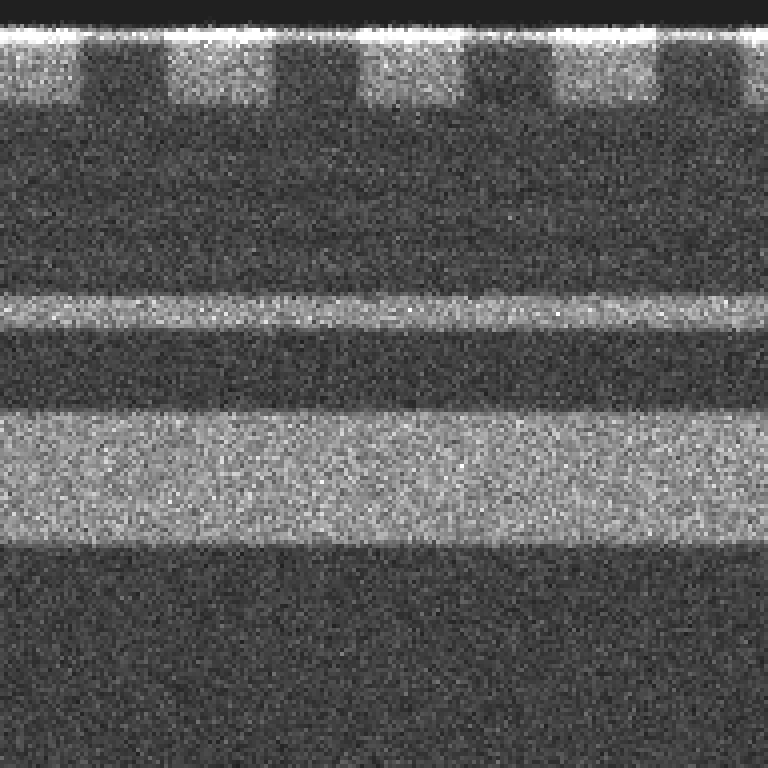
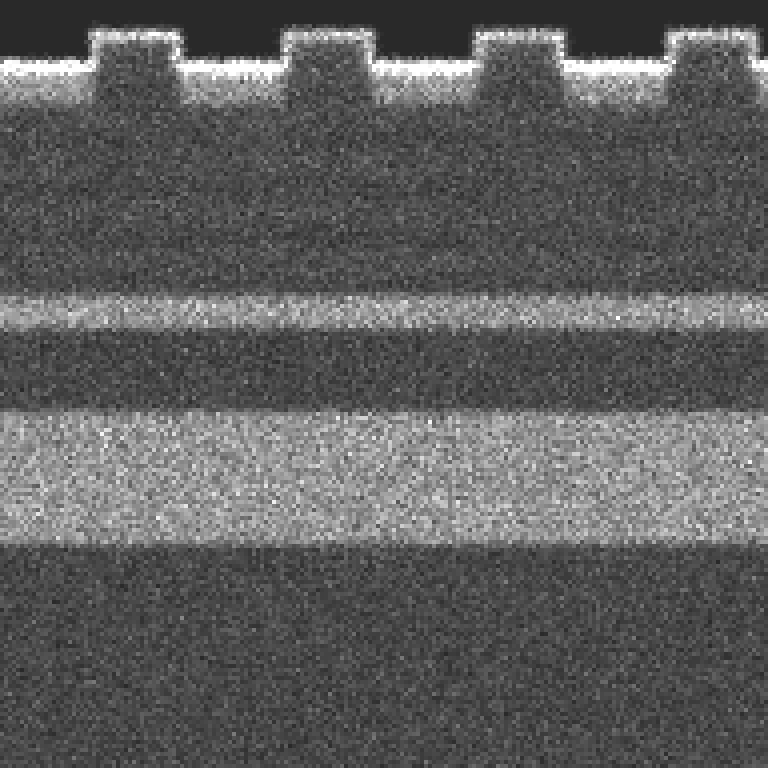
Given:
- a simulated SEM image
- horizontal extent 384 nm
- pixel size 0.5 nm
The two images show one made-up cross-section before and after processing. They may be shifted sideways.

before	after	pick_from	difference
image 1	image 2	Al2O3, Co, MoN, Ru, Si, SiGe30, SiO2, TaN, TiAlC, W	Co removed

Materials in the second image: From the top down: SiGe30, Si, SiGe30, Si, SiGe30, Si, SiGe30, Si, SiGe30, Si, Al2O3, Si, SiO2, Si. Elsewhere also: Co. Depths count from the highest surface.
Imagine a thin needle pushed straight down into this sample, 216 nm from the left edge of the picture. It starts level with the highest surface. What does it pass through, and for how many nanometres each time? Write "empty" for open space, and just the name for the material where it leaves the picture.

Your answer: empty 16, Co 20, SiGe30 14, Si 10, SiGe30 14, Si 10, SiGe30 14, Si 10, SiGe30 14, Si 10, Al2O3 16, Si 42, SiO2 66, Si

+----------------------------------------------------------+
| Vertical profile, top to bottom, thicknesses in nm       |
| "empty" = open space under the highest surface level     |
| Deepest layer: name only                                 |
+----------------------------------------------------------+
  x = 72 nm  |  SiGe30 26, Si 10, SiGe30 14, Si 10, SiGe30 14, Si 10, SiGe30 14, Si 10, SiGe30 14, Si 10, Al2O3 16, Si 42, SiO2 66, Si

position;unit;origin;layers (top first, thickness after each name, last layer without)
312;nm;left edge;empty 16, Co 20, SiGe30 14, Si 10, SiGe30 14, Si 10, SiGe30 14, Si 10, SiGe30 14, Si 10, Al2O3 16, Si 42, SiO2 66, Si